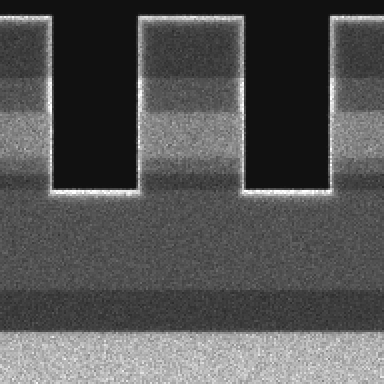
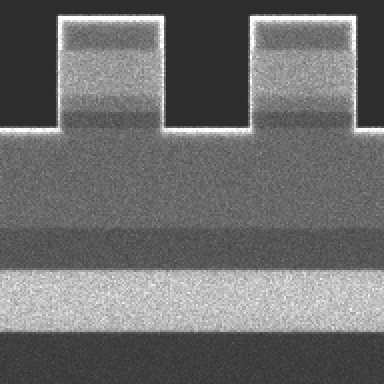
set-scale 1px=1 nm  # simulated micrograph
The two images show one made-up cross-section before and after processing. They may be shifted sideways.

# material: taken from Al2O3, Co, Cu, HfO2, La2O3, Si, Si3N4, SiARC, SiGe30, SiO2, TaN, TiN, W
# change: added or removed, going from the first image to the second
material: SiARC
change: removed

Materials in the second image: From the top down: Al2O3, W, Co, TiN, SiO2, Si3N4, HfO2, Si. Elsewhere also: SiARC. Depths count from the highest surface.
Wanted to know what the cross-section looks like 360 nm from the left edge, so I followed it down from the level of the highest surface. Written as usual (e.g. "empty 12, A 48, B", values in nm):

empty 112, SiO2 100, Si3N4 42, HfO2 62, Si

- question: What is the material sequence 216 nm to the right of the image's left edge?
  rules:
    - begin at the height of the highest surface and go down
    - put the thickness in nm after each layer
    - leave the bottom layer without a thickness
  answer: empty 112, SiO2 100, Si3N4 42, HfO2 62, Si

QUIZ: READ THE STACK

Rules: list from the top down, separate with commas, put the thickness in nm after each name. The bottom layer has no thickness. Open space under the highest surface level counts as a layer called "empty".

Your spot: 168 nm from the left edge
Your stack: empty 112, SiO2 100, Si3N4 42, HfO2 62, Si